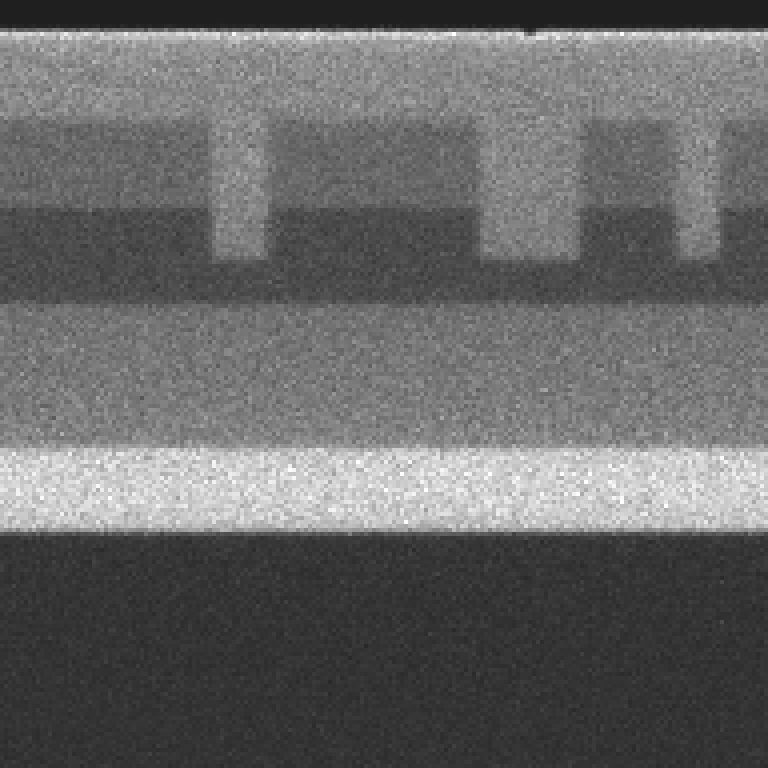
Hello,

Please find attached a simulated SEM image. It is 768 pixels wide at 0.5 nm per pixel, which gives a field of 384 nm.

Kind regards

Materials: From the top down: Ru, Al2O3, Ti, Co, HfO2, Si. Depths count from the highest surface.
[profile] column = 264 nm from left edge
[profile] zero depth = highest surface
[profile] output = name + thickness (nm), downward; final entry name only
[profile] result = empty 2, Ru 112, Ti 22, Co 72, HfO2 42, Si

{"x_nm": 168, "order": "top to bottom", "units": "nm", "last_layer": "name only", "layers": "Ru 44, Al2O3 44, Ti 48, Co 72, HfO2 42, Si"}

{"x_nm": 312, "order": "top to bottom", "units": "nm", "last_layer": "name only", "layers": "Ru 44, Al2O3 44, Ti 48, Co 72, HfO2 42, Si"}